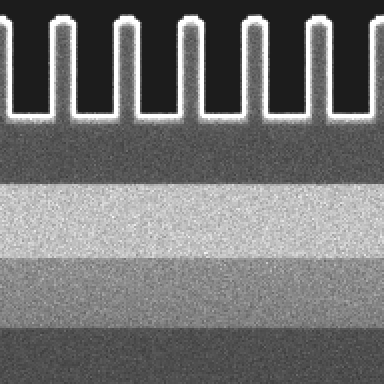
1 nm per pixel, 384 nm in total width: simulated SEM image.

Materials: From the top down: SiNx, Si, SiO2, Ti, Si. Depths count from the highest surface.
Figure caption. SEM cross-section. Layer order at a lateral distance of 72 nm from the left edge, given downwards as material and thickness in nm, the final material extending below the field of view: empty 4, SiNx 104, Si 60, SiO2 74, Ti 70, Si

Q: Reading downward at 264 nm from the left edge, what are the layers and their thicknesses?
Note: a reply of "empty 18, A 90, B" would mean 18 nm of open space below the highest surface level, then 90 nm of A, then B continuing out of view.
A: empty 4, SiNx 104, Si 60, SiO2 74, Ti 70, Si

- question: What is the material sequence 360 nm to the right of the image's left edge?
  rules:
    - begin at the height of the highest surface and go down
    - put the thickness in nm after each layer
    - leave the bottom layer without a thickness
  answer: empty 98, SiNx 10, Si 60, SiO2 74, Ti 70, Si